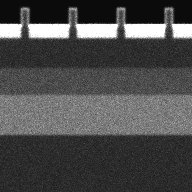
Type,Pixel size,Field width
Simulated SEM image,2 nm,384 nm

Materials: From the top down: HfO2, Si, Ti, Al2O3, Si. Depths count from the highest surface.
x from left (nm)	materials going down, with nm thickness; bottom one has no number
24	empty 34, HfO2 26, Si 60, Ti 54, Al2O3 80, Si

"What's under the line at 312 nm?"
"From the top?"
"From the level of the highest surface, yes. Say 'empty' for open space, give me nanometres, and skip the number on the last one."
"empty 34, HfO2 26, Si 60, Ti 54, Al2O3 80, Si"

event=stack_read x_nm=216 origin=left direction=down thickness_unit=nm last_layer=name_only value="empty 34, HfO2 26, Si 60, Ti 54, Al2O3 80, Si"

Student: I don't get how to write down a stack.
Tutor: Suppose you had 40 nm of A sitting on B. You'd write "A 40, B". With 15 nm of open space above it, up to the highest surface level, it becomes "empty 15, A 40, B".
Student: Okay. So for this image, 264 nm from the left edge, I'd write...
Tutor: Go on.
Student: empty 34, HfO2 26, Si 60, Ti 54, Al2O3 80, Si